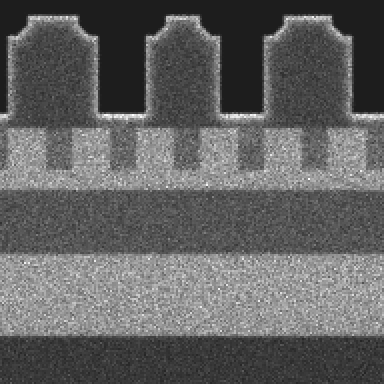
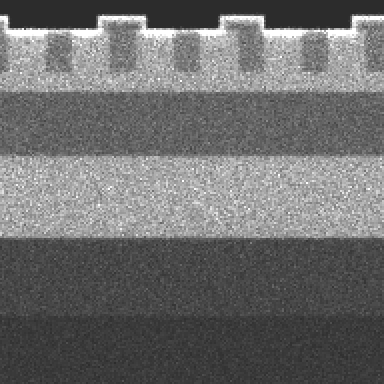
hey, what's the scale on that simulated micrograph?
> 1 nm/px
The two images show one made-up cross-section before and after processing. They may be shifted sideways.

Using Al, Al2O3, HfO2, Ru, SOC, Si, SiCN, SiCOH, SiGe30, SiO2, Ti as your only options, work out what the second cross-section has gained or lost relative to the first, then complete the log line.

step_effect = removed SOC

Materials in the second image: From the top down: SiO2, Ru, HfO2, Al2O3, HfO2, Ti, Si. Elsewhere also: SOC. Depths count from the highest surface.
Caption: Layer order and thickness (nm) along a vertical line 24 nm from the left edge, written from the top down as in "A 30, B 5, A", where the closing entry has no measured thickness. empty 14, HfO2 62, Al2O3 64, HfO2 82, Ti 78, Si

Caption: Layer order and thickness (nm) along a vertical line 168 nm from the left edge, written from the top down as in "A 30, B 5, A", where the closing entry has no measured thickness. empty 14, HfO2 62, Al2O3 64, HfO2 82, Ti 78, Si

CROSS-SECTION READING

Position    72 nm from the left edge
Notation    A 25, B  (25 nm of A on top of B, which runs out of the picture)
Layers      empty 14, HfO2 62, Al2O3 64, HfO2 82, Ti 78, Si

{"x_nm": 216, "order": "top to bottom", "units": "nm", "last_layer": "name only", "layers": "empty 14, HfO2 62, Al2O3 64, HfO2 82, Ti 78, Si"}